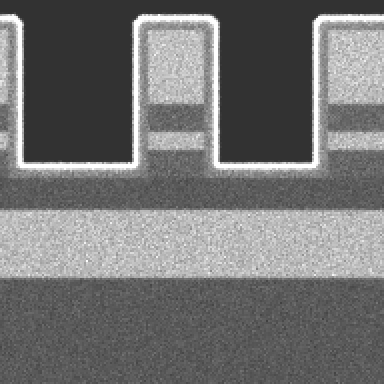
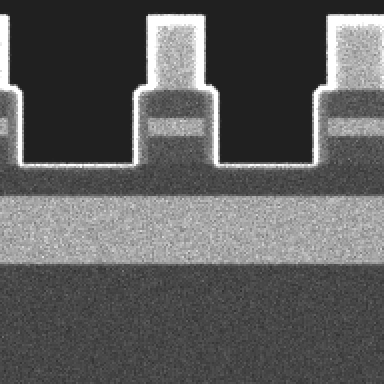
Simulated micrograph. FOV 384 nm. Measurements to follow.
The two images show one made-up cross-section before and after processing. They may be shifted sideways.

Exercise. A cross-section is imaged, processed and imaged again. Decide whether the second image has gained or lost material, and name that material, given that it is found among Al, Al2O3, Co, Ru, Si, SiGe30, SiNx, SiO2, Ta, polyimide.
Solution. removed: SiNx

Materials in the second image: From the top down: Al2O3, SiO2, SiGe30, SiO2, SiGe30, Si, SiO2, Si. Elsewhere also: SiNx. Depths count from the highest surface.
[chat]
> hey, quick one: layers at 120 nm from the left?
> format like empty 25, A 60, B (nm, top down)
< empty 148, Si 32, SiO2 68, Si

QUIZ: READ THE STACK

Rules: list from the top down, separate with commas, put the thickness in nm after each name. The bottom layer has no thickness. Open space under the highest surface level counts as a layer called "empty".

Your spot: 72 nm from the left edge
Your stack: empty 148, Si 32, SiO2 68, Si